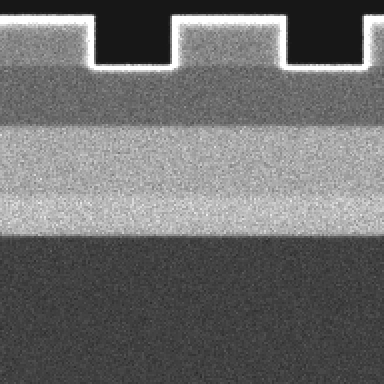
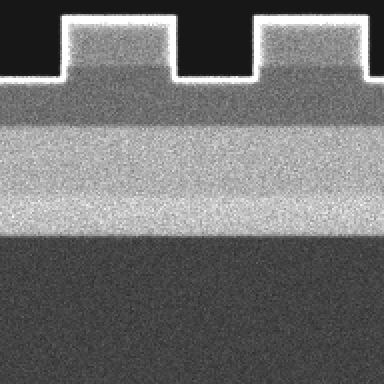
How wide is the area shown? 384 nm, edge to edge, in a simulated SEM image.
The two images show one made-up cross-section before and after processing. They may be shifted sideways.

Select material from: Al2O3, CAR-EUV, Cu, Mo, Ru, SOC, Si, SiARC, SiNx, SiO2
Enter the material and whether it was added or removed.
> SiNx / removed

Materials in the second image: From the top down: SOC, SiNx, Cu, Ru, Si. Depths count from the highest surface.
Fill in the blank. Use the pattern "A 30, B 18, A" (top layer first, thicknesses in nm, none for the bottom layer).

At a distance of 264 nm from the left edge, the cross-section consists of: SOC 50, SiNx 60, Cu 70, Ru 40, Si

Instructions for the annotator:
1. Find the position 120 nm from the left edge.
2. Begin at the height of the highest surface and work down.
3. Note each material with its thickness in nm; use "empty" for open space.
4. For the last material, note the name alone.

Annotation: SOC 50, SiNx 60, Cu 70, Ru 40, Si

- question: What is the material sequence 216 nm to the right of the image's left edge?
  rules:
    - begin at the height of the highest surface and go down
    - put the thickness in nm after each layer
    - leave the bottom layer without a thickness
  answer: empty 62, SiNx 48, Cu 70, Ru 40, Si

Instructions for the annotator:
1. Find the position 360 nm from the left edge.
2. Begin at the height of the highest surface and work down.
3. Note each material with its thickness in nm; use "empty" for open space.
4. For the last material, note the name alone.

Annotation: SOC 50, SiNx 60, Cu 70, Ru 40, Si